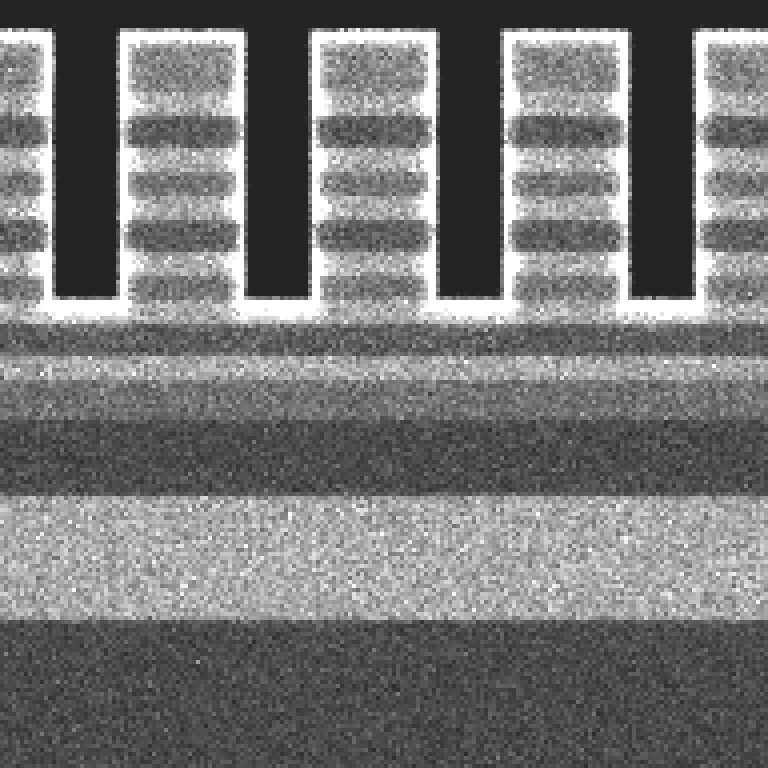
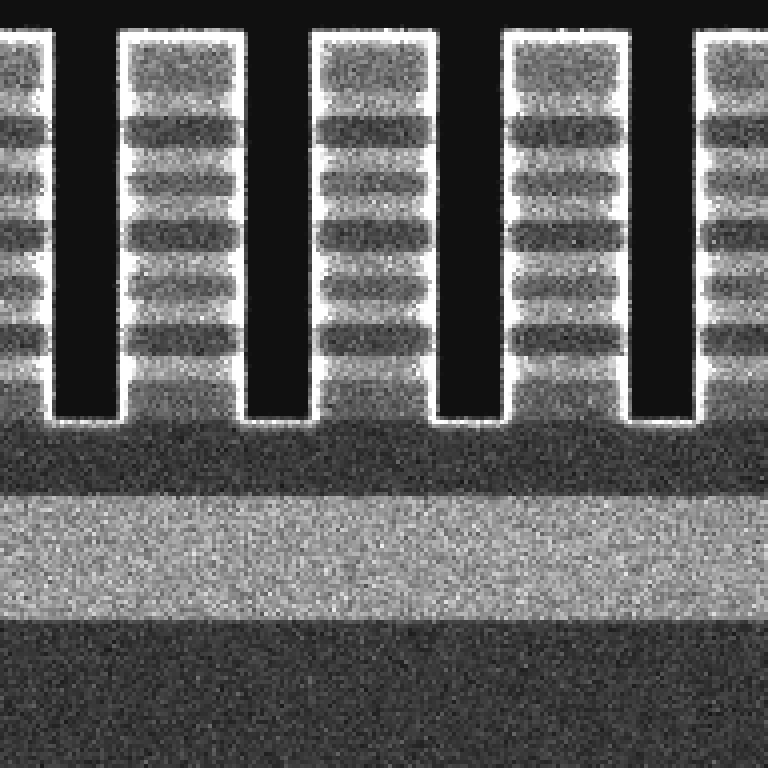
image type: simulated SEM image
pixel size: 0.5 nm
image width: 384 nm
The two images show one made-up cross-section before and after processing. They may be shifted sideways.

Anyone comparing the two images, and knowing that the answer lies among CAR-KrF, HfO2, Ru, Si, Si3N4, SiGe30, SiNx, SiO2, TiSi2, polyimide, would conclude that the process removed SiGe30 and SiNx and SiO2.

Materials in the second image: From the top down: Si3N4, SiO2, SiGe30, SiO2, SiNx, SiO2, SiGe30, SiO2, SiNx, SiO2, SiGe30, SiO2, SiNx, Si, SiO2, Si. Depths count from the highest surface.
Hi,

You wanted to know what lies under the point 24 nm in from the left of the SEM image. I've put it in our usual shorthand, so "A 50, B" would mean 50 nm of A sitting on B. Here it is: Si3N4 30, SiO2 12, SiGe30 16, SiO2 12, SiNx 12, SiO2 12, SiGe30 16, SiO2 12, SiNx 12, SiO2 12, SiGe30 16, SiO2 12, SiNx 20, Si 38, SiO2 62, Si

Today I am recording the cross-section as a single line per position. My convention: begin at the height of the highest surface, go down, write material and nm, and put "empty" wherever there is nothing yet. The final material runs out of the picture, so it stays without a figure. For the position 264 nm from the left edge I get Si3N4 30, SiO2 12, SiGe30 16, SiO2 12, SiNx 12, SiO2 12, SiGe30 16, SiO2 12, SiNx 12, SiO2 12, SiGe30 16, SiO2 12, SiNx 20, Si 38, SiO2 62, Si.